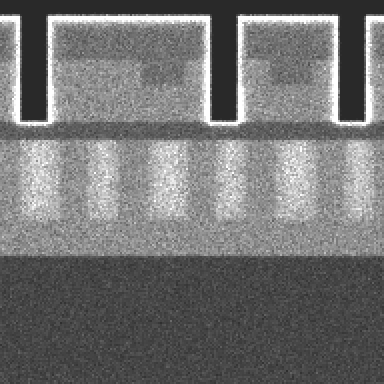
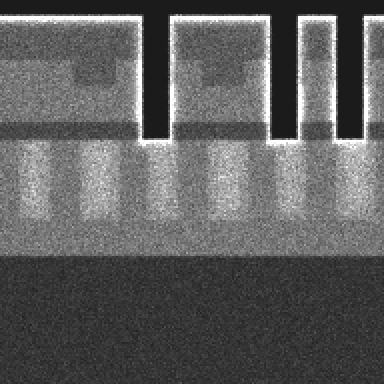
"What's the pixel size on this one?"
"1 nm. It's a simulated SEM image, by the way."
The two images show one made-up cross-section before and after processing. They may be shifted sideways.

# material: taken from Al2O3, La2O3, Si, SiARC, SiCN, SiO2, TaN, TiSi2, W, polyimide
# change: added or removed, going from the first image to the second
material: SiCN
change: removed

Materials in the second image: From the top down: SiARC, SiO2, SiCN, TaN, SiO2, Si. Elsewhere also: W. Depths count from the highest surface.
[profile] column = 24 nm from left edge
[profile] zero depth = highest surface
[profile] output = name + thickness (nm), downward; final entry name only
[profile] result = SiARC 44, SiO2 62, SiCN 18, TaN 80, SiO2 36, Si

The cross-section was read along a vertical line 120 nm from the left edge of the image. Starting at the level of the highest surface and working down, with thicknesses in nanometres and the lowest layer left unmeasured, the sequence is SiARC 44, SiO2 62, SiCN 18, SiO2 116, Si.